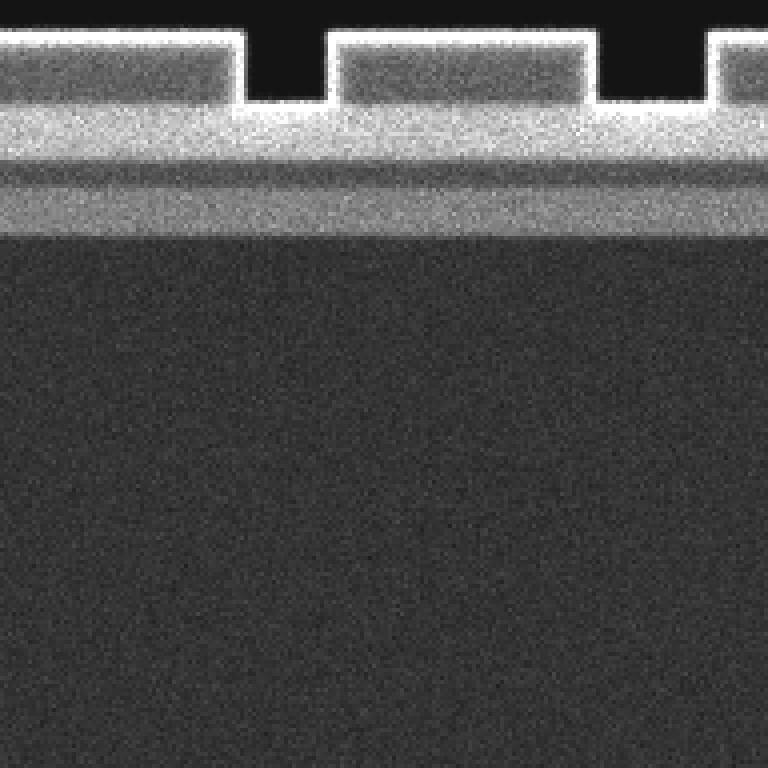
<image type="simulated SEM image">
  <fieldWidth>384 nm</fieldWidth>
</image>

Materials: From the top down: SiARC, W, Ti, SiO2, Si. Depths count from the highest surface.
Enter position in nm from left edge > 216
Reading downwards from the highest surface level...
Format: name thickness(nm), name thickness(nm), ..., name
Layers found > SiARC 36, W 28, Ti 14, SiO2 24, Si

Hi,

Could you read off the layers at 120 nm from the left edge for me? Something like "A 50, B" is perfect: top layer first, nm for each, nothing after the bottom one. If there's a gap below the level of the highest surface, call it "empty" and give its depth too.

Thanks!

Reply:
SiARC 36, W 28, Ti 14, SiO2 24, Si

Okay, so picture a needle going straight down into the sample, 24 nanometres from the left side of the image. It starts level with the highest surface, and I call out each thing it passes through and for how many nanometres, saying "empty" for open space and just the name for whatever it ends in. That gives SiARC 36, W 28, Ti 14, SiO2 24, Si